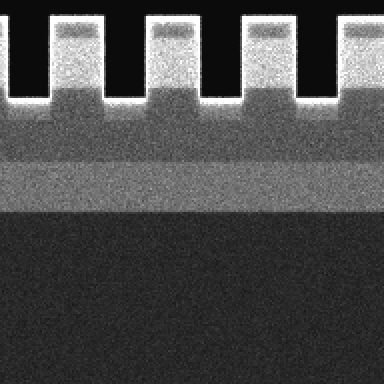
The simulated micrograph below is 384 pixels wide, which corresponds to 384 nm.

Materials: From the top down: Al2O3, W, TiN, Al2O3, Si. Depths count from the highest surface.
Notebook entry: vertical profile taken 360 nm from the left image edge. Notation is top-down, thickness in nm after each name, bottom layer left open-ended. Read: Al2O3 22, W 50, TiN 74, Al2O3 50, Si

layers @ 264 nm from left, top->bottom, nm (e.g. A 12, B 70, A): Al2O3 22, W 50, TiN 74, Al2O3 50, Si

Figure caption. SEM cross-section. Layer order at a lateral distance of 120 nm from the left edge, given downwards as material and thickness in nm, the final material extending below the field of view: empty 82, Al2O3 22, TiN 42, Al2O3 50, Si